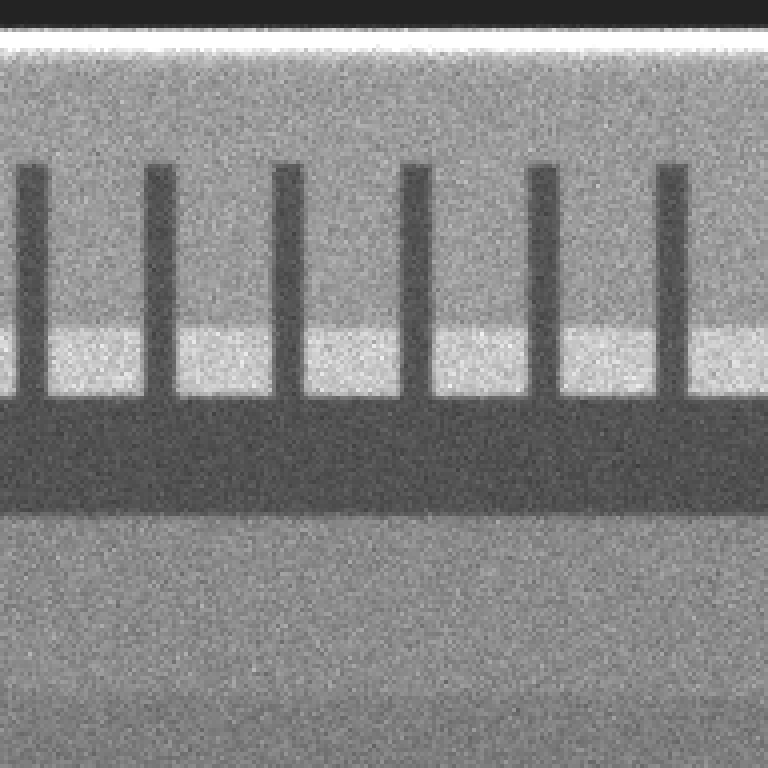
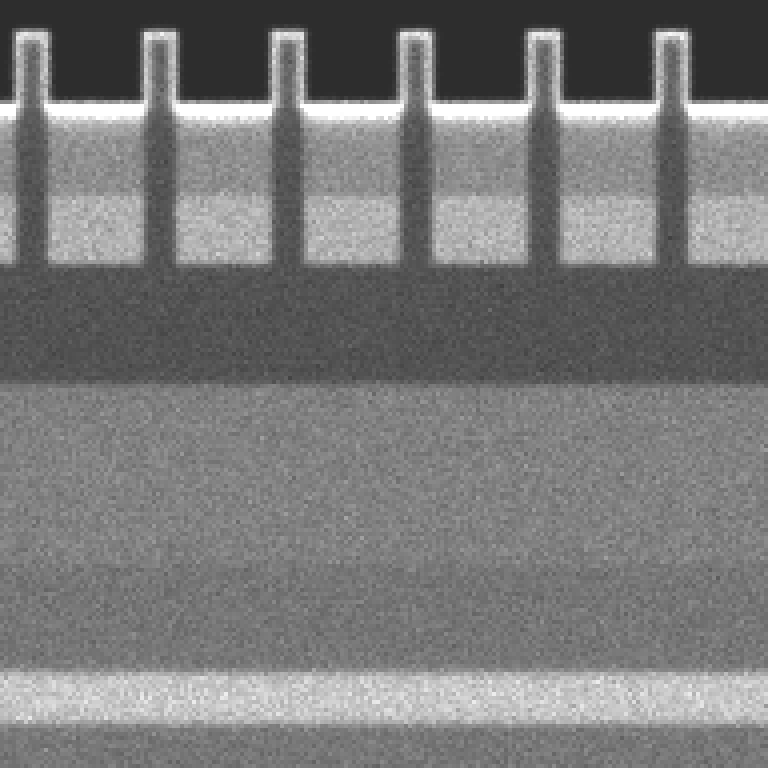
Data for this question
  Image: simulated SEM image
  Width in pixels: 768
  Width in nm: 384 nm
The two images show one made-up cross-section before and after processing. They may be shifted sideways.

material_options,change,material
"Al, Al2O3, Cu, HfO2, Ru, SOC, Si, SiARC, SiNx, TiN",removed,SOC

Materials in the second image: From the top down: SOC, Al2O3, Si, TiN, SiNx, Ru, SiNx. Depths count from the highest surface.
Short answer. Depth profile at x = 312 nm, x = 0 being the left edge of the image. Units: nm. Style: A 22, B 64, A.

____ empty 36, SOC 46, Al2O3 34, Si 60, TiN 90, SiNx 54, Ru 26, SiNx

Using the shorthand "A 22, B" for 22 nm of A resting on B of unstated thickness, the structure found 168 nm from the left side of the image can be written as empty 36, SOC 46, Al2O3 34, Si 60, TiN 90, SiNx 54, Ru 26, SiNx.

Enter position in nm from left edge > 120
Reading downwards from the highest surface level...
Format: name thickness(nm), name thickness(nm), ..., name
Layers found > empty 36, SOC 46, Al2O3 34, Si 60, TiN 90, SiNx 54, Ru 26, SiNx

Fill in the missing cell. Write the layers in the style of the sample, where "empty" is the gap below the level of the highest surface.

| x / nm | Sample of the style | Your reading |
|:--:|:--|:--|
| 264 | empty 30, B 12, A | Si 176, TiN 90, SiNx 54, Ru 26, SiNx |